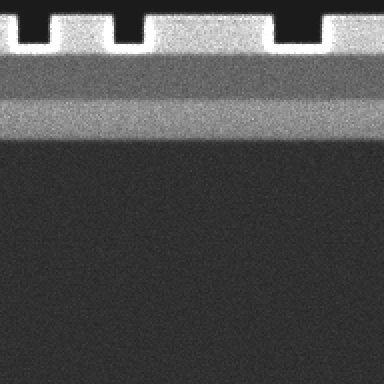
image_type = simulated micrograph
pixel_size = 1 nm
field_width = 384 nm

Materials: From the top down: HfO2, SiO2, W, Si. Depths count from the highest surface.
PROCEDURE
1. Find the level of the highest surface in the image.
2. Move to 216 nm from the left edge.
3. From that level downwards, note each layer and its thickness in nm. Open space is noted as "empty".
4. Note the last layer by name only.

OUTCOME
HfO2 38, SiO2 46, W 40, Si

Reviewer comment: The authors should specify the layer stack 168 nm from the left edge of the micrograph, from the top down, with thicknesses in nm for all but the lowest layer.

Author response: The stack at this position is HfO2 38, SiO2 46, W 40, Si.